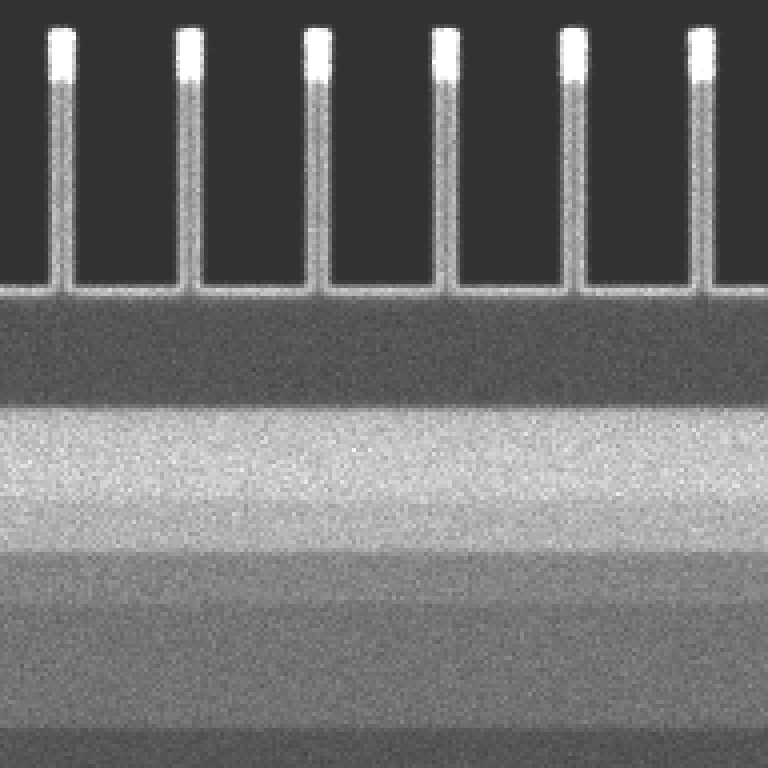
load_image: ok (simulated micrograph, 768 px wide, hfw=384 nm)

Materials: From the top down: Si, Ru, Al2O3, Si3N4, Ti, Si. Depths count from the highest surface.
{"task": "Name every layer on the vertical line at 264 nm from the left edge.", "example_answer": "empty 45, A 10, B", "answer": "empty 128, Si 60, Ru 46, Al2O3 26, Si3N4 26, Ti 62, Si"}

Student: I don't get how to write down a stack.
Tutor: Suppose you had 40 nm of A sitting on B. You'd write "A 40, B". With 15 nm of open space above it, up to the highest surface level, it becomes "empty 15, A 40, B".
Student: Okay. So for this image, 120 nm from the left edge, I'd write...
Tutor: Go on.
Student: empty 128, Si 60, Ru 46, Al2O3 26, Si3N4 26, Ti 62, Si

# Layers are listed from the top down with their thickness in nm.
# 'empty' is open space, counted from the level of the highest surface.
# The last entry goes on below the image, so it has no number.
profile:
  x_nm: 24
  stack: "empty 128, Si 60, Ru 46, Al2O3 26, Si3N4 26, Ti 62, Si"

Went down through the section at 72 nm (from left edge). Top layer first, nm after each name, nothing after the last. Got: empty 128, Si 60, Ru 46, Al2O3 26, Si3N4 26, Ti 62, Si